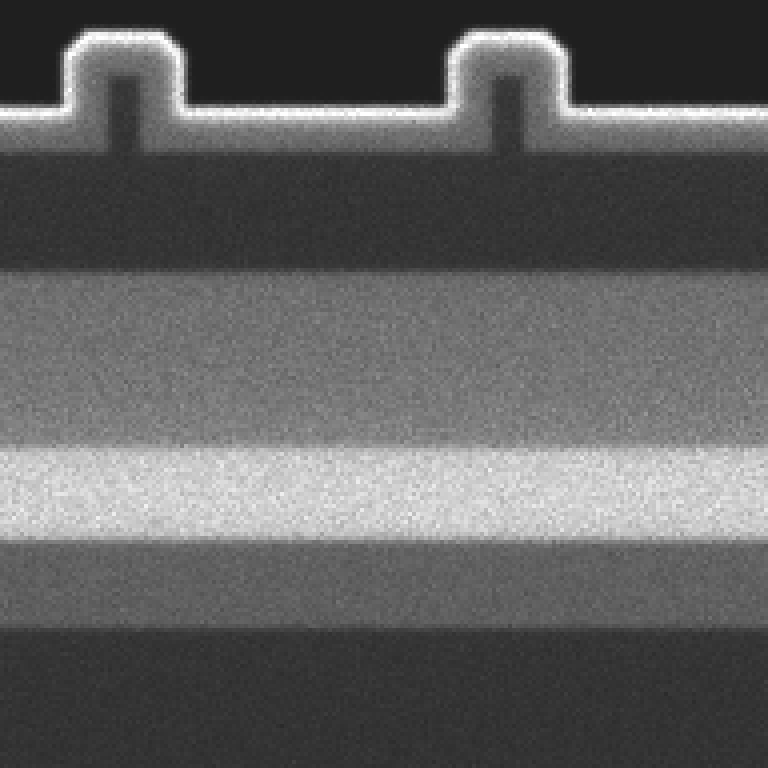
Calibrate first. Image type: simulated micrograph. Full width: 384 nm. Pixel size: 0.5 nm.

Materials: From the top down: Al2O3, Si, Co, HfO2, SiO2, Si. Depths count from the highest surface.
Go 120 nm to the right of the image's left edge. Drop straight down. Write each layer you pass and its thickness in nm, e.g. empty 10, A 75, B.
empty 38, Al2O3 22, Si 60, Co 88, HfO2 46, SiO2 44, Si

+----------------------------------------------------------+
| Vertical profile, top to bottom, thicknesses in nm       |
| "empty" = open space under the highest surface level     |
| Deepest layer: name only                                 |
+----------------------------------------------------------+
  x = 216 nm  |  empty 38, Al2O3 22, Si 60, Co 88, HfO2 46, SiO2 44, Si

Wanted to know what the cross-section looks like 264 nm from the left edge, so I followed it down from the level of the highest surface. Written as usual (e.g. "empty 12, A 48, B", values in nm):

Al2O3 60, Si 60, Co 88, HfO2 46, SiO2 44, Si